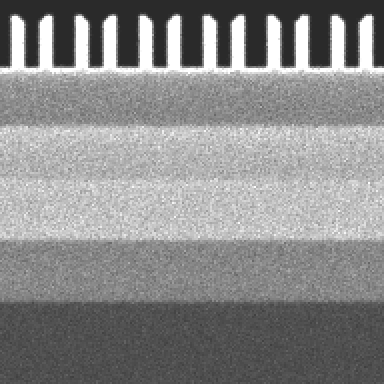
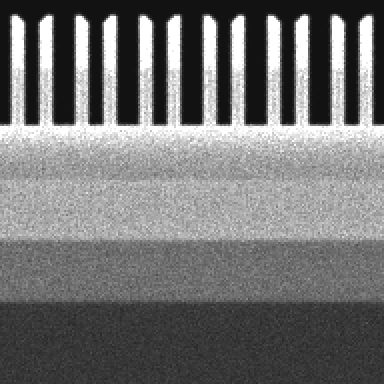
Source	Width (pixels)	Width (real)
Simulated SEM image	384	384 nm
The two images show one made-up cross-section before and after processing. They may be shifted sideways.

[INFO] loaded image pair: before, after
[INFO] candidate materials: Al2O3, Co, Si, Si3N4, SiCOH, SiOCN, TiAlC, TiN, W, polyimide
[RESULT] removed Si3N4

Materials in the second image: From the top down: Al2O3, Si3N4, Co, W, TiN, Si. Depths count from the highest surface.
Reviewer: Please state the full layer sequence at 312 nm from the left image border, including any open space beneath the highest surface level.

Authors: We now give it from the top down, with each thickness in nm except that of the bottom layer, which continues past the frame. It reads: empty 110, Co 54, W 60, TiN 62, Si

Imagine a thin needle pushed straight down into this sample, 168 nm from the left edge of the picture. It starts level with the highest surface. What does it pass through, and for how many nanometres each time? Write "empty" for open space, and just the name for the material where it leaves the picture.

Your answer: empty 6, Al2O3 46, Si3N4 58, Co 54, W 60, TiN 62, Si